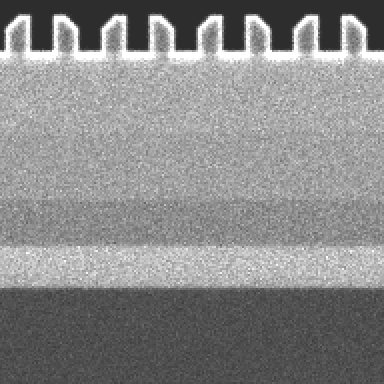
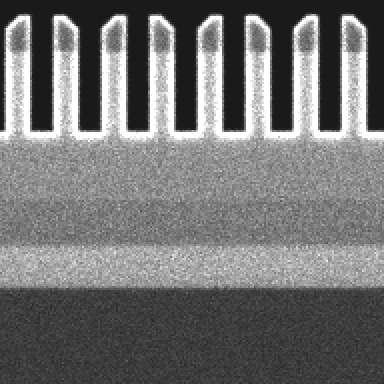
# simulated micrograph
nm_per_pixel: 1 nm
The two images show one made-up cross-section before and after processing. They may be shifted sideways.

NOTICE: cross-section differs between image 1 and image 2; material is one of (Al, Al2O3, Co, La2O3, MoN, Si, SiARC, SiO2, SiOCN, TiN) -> removed: Al2O3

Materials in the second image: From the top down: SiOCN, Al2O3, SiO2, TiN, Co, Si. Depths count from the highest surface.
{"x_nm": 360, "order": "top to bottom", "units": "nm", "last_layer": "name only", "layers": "empty 8, SiOCN 28, Al2O3 80, SiO2 68, TiN 46, Co 42, Si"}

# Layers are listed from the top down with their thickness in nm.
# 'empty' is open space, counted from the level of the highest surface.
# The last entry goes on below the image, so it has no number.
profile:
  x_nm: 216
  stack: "SiOCN 36, Al2O3 80, SiO2 68, TiN 46, Co 42, Si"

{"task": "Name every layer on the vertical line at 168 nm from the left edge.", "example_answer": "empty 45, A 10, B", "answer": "empty 8, SiOCN 28, Al2O3 80, SiO2 68, TiN 46, Co 42, Si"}